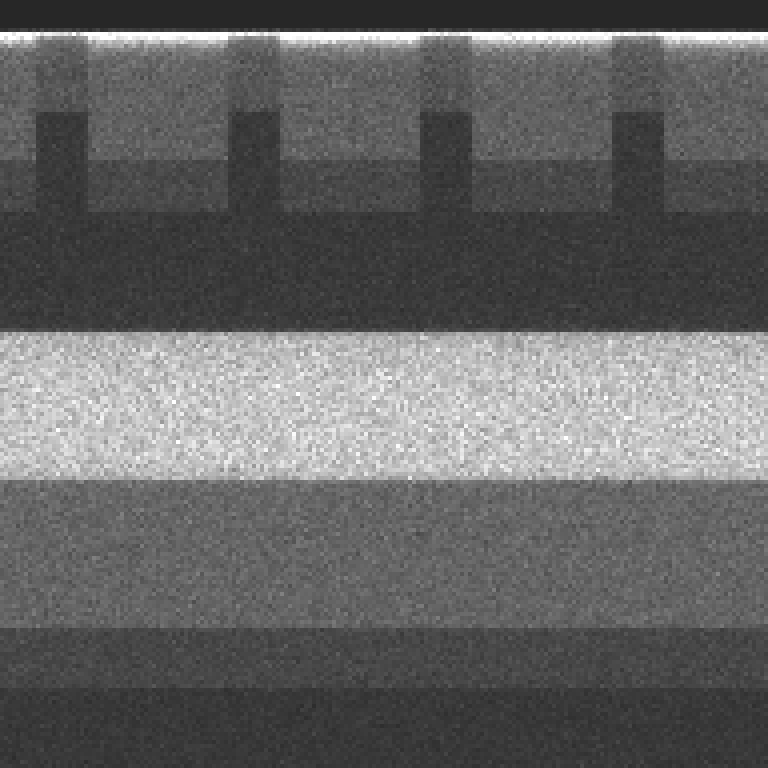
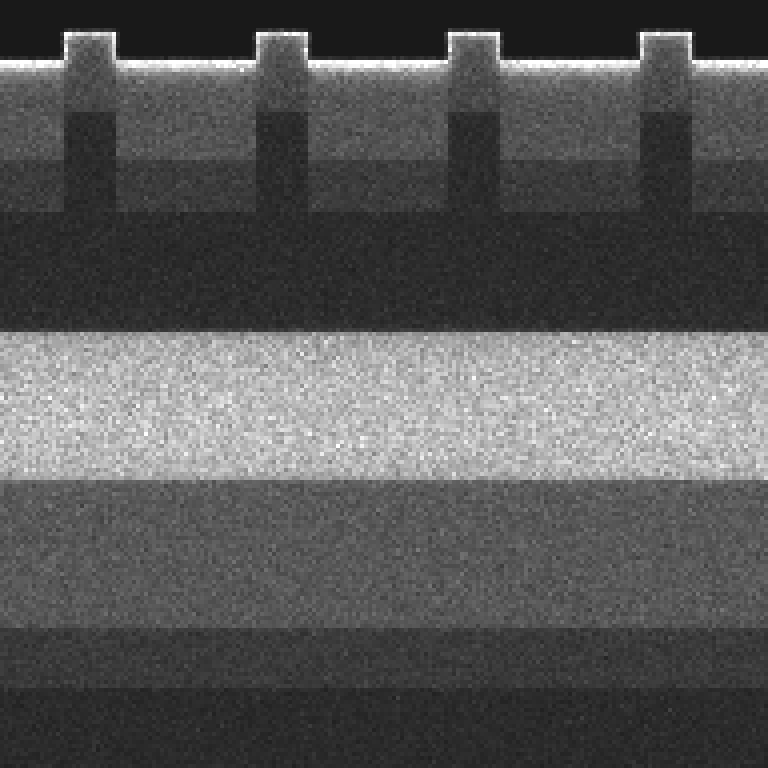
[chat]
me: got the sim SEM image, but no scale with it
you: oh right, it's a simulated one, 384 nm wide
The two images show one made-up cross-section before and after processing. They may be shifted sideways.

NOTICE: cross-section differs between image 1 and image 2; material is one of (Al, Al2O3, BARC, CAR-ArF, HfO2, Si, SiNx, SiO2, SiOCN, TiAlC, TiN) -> removed: SiO2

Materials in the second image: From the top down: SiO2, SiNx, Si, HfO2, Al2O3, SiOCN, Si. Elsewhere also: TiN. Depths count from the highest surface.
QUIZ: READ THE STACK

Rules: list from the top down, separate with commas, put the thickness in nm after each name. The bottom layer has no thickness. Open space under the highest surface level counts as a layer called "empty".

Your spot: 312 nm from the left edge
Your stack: empty 14, SiO2 50, SiNx 26, Si 60, HfO2 74, Al2O3 74, SiOCN 30, Si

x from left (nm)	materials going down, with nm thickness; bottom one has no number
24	empty 14, SiO2 50, SiNx 26, Si 60, HfO2 74, Al2O3 74, SiOCN 30, Si